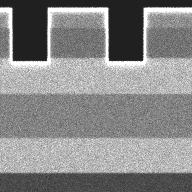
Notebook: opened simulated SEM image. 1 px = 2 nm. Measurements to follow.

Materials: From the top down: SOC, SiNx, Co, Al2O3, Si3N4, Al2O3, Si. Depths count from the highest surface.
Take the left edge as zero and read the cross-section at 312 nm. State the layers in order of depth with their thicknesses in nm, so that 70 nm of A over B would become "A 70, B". SOC 40, SiNx 60, Co 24, Al2O3 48, Si3N4 88, Al2O3 70, Si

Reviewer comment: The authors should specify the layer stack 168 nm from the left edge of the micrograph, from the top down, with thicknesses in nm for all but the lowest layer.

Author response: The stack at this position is SOC 40, SiNx 60, Co 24, Al2O3 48, Si3N4 88, Al2O3 70, Si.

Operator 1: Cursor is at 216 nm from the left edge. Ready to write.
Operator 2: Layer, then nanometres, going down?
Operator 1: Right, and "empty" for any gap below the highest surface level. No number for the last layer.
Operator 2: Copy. empty 108, Co 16, Al2O3 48, Si3N4 88, Al2O3 70, Si